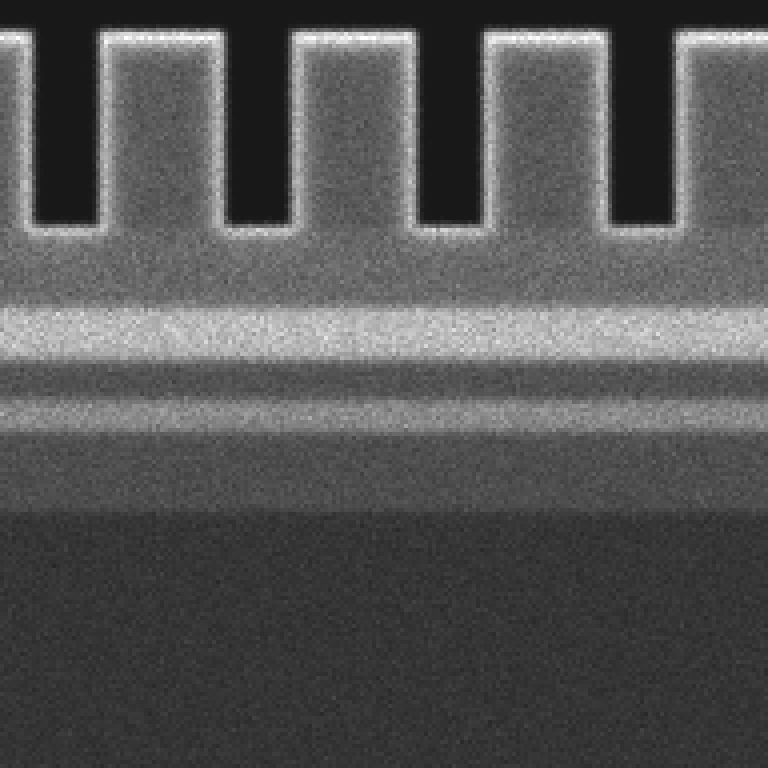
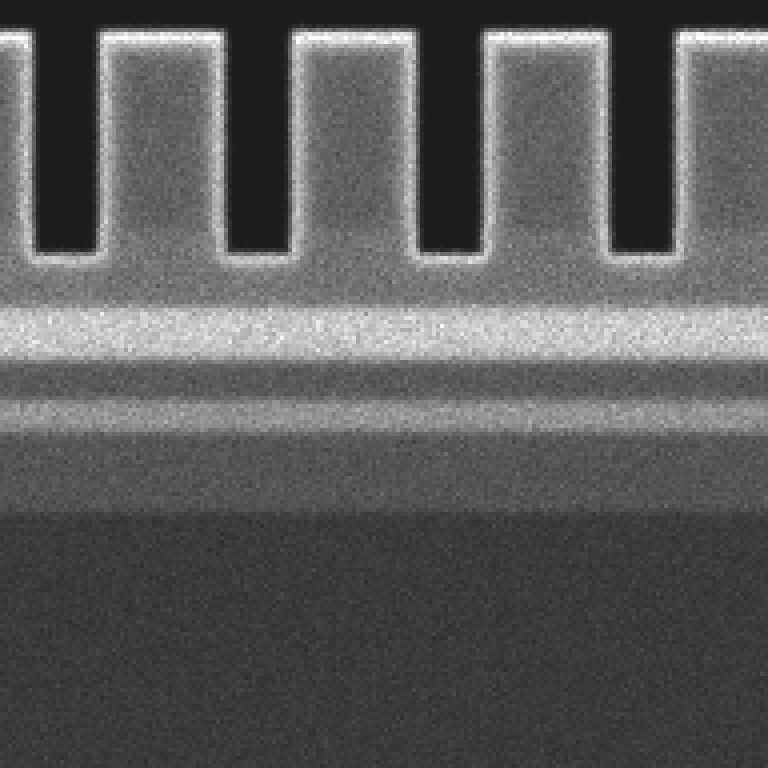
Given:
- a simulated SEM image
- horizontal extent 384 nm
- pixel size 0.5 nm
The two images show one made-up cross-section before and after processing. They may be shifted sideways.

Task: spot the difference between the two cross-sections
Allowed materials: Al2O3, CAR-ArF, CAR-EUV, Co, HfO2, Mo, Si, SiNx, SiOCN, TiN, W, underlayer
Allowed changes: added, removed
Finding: removed TiN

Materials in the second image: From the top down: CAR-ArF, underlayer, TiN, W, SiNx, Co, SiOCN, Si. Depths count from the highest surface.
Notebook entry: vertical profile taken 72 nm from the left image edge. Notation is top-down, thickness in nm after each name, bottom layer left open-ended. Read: CAR-ArF 78, underlayer 20, TiN 40, W 26, SiNx 20, Co 16, SiOCN 40, Si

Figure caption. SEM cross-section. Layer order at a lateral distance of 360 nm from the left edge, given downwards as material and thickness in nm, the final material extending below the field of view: CAR-ArF 78, underlayer 20, TiN 40, W 26, SiNx 20, Co 16, SiOCN 40, Si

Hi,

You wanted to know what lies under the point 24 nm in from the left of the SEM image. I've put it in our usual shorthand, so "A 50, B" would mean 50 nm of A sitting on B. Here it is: empty 112, TiN 26, W 26, SiNx 20, Co 16, SiOCN 40, Si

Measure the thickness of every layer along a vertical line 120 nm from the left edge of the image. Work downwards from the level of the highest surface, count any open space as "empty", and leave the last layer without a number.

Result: empty 112, TiN 26, W 26, SiNx 20, Co 16, SiOCN 40, Si